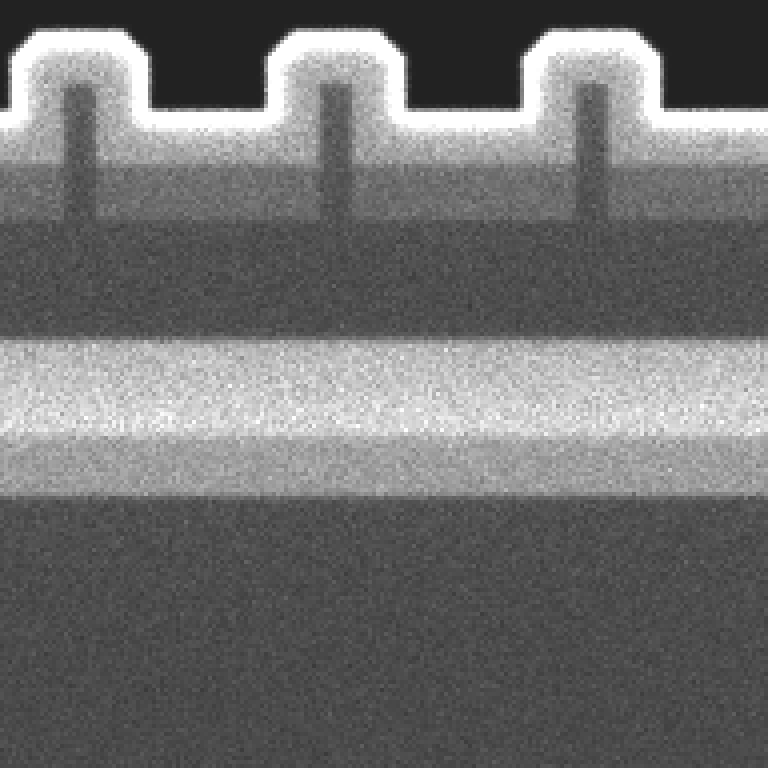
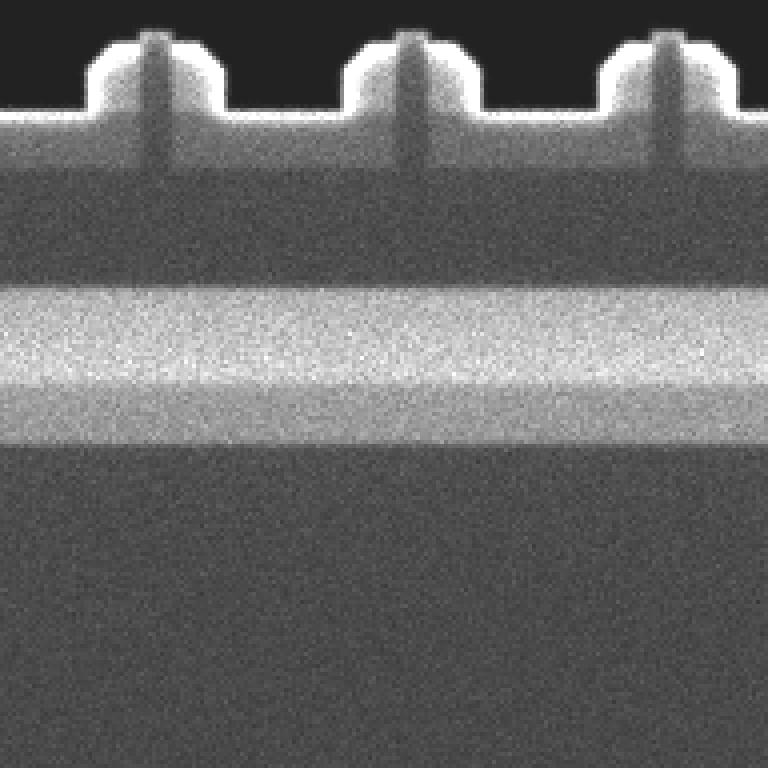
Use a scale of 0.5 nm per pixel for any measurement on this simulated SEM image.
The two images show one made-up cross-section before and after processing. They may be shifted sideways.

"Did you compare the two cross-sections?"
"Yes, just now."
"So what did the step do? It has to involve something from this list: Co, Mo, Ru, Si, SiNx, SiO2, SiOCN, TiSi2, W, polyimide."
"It removed SiO2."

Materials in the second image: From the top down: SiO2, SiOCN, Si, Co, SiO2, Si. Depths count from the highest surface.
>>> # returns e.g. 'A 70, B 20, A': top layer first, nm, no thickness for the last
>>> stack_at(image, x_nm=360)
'empty 12, SiO2 28, SiOCN 28, Si 60, Co 48, SiO2 30, Si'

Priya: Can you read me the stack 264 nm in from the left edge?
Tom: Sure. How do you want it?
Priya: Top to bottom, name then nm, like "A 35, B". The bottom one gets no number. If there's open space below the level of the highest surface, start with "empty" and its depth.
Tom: empty 40, SiOCN 28, Si 60, Co 48, SiO2 30, Si